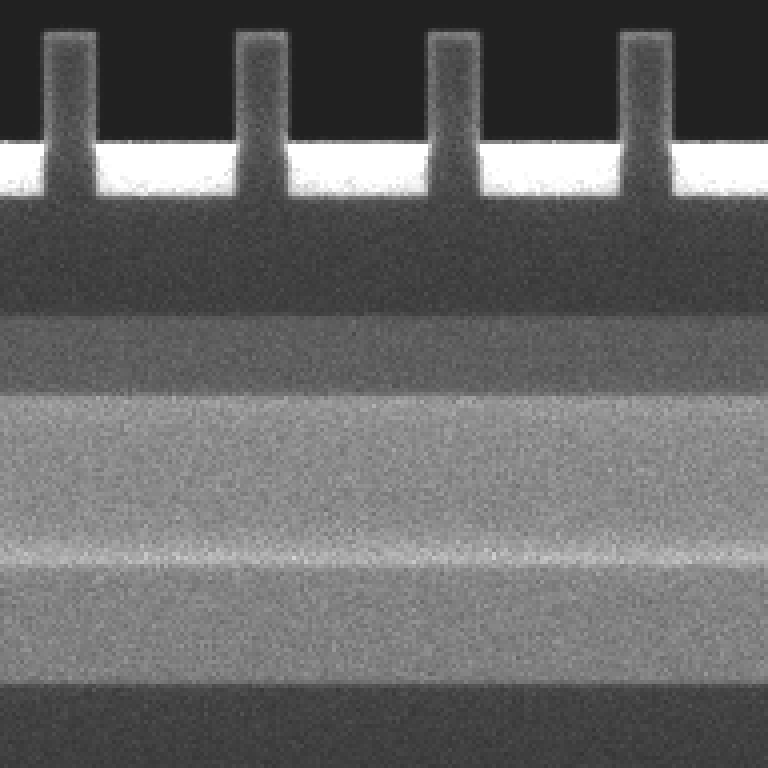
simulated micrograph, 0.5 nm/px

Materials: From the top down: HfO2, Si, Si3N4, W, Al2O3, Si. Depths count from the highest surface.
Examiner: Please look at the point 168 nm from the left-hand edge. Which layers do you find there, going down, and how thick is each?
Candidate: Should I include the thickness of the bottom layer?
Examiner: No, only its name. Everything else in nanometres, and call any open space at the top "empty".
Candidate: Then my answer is empty 56, HfO2 26, Si 60, Si3N4 40, W 84, Al2O3 60, Si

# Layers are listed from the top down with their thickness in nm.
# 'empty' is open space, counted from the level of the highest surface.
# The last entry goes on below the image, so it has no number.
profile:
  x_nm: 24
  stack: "Si 142, Si3N4 40, W 84, Al2O3 60, Si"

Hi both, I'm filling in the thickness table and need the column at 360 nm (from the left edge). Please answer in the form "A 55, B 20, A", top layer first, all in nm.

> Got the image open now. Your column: empty 56, HfO2 26, Si 60, Si3N4 40, W 84, Al2O3 60, Si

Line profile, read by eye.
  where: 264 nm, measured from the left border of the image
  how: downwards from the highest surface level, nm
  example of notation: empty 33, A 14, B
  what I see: empty 56, HfO2 26, Si 60, Si3N4 40, W 84, Al2O3 60, Si